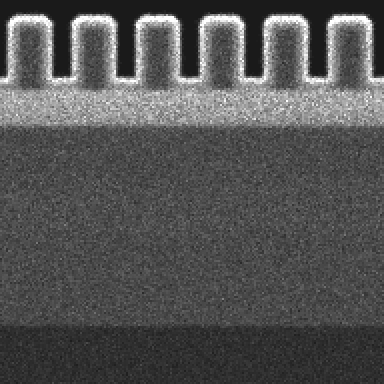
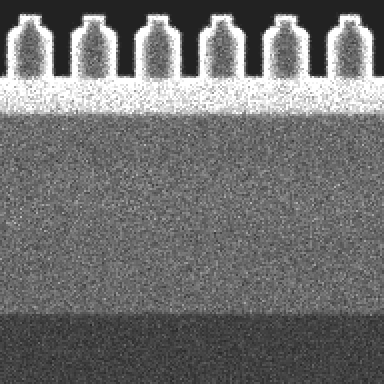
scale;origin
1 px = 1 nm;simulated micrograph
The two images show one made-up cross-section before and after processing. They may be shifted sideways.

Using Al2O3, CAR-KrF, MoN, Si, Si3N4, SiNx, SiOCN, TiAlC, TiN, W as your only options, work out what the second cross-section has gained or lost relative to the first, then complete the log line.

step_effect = removed Al2O3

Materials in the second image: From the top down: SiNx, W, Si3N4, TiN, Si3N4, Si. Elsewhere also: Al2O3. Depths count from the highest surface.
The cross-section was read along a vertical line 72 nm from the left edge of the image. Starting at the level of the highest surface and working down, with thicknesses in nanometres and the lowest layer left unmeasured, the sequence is empty 18, Al2O3 44, W 36, Si3N4 56, TiN 56, Si3N4 88, Si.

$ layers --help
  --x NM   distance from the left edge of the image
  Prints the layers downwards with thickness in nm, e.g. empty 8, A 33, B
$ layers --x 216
SiNx 62, W 36, Si3N4 56, TiN 56, Si3N4 88, Si